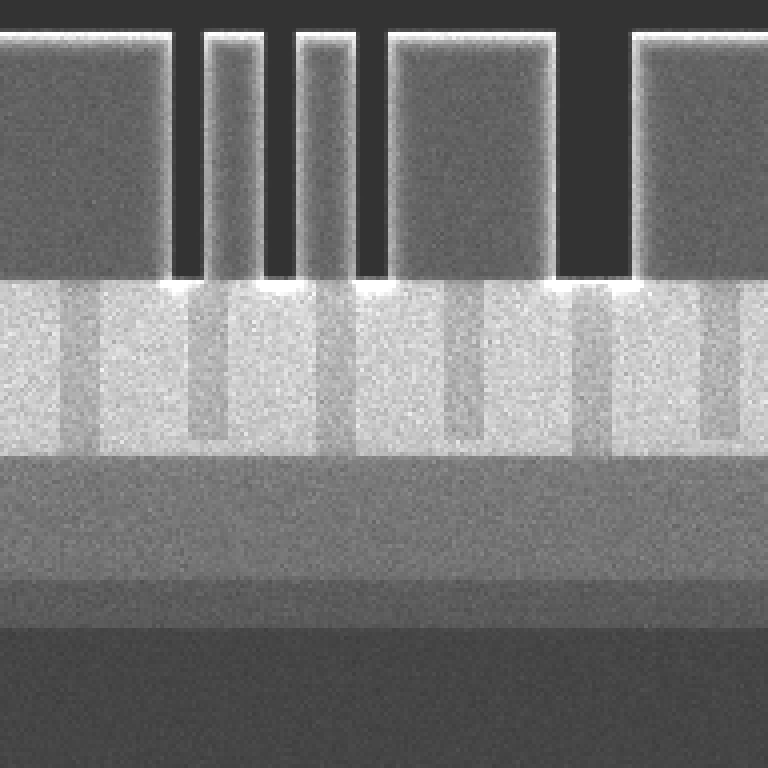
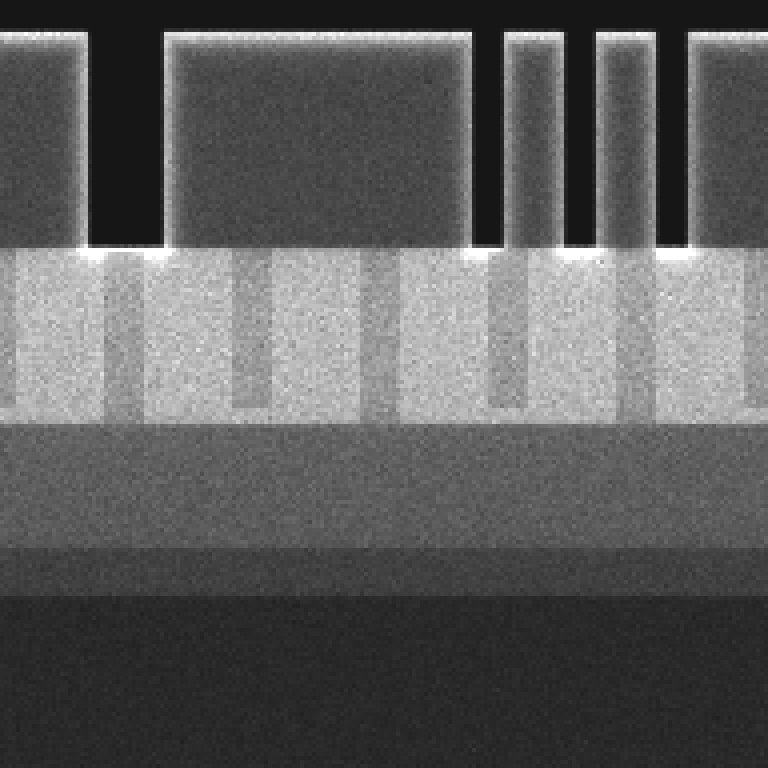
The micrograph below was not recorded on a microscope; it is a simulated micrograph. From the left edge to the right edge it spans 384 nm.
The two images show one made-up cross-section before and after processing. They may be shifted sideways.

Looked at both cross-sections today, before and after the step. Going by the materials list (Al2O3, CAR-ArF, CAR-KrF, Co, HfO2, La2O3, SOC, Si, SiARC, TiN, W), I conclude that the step removed SiARC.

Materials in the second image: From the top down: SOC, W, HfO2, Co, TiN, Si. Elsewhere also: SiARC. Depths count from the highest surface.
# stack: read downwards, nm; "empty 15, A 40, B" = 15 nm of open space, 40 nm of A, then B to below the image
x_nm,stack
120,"SOC 108, W 80, HfO2 8, Co 62, TiN 24, Si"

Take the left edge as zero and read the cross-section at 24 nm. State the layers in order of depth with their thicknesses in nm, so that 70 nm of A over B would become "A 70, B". SOC 108, HfO2 88, Co 62, TiN 24, Si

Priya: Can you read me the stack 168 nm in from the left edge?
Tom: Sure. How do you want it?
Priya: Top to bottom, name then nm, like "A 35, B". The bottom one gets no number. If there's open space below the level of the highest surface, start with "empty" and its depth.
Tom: SOC 108, HfO2 88, Co 62, TiN 24, Si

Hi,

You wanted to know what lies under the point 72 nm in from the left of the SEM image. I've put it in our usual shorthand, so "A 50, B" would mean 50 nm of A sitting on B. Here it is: empty 108, HfO2 88, Co 62, TiN 24, Si